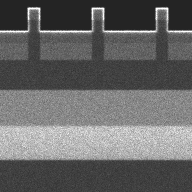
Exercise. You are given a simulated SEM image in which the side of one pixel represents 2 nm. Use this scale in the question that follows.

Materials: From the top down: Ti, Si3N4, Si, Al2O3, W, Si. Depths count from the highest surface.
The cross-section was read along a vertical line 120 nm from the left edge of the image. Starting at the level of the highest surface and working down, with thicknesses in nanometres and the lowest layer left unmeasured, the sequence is empty 46, Ti 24, Si3N4 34, Si 60, Al2O3 72, W 68, Si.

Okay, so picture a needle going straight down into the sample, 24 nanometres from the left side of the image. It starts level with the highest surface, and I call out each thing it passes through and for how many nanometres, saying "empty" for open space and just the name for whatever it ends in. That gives empty 46, Ti 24, Si3N4 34, Si 60, Al2O3 72, W 68, Si